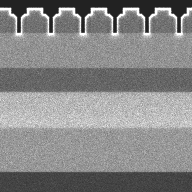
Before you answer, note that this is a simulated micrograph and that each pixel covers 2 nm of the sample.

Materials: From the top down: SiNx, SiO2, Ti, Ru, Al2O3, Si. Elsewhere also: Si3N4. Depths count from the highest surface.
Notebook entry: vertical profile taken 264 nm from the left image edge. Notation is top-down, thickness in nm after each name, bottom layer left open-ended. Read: Si3N4 50, SiO2 70, Ti 48, Ru 72, Al2O3 88, Si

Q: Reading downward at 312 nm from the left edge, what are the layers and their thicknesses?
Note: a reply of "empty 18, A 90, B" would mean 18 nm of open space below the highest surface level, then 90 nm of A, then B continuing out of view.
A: Si3N4 50, SiO2 70, Ti 48, Ru 72, Al2O3 88, Si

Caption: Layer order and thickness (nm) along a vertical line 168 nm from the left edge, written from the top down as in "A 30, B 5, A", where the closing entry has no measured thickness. empty 50, SiO2 70, Ti 48, Ru 72, Al2O3 88, Si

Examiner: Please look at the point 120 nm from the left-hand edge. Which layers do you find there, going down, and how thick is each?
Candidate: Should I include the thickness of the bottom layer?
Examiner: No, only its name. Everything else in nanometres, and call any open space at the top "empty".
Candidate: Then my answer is Si3N4 50, SiO2 70, Ti 48, Ru 72, Al2O3 88, Si